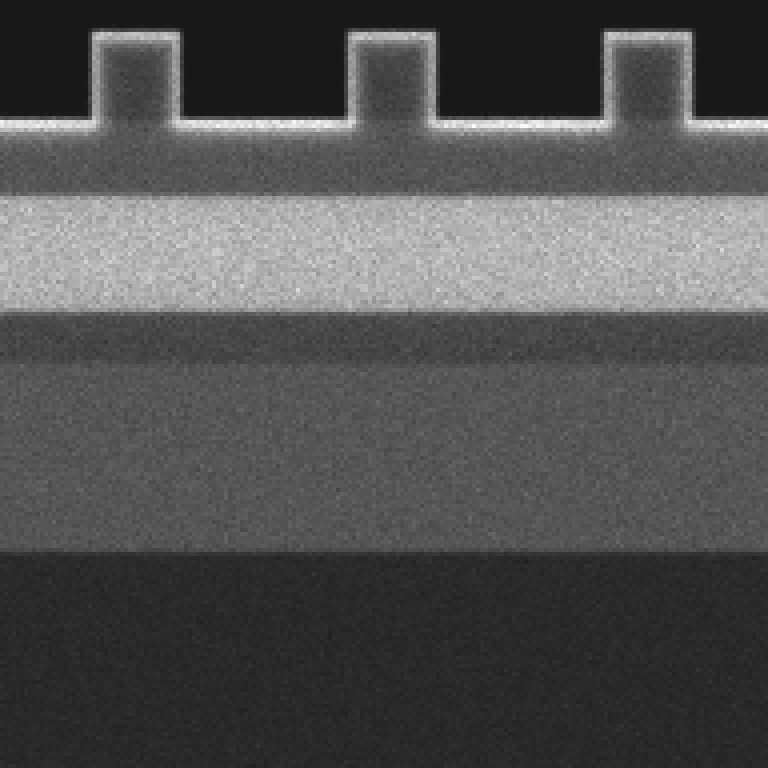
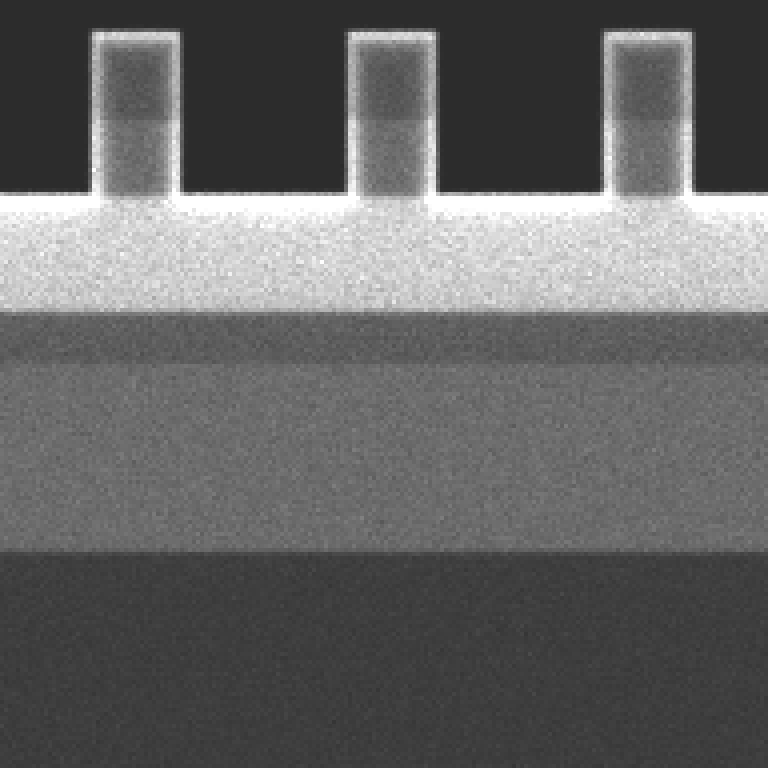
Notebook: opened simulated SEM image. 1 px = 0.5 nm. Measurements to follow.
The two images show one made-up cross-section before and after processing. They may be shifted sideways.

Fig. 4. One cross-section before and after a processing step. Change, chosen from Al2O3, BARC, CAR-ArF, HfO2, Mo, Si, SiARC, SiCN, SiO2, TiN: SiO2 removed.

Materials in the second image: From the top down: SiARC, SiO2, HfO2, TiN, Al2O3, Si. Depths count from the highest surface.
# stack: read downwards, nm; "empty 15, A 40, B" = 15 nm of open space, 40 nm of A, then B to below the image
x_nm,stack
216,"SiARC 44, SiO2 38, HfO2 58, TiN 26, Al2O3 94, Si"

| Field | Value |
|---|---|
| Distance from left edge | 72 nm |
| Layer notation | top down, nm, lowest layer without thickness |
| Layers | SiARC 44, SiO2 38, HfO2 58, TiN 26, Al2O3 94, Si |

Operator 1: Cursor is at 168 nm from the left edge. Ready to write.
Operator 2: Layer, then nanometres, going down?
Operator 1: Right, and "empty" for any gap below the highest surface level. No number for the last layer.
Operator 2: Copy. empty 82, HfO2 58, TiN 26, Al2O3 94, Si